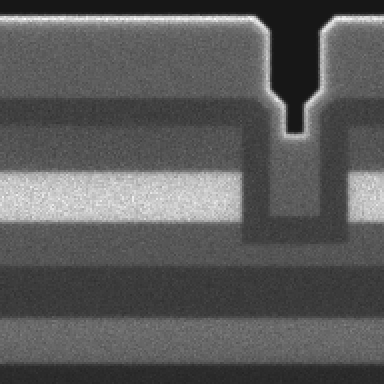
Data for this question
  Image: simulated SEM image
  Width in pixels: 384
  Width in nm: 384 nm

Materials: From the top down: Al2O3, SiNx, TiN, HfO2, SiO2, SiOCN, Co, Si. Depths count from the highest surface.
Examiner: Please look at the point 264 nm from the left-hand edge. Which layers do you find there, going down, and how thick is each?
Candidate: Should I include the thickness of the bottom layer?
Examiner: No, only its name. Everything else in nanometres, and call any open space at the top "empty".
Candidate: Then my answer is empty 10, Al2O3 82, SiNx 136, SiO2 22, SiOCN 52, Co 46, Si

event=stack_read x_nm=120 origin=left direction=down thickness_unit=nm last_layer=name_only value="Al2O3 82, SiNx 28, TiN 46, HfO2 50, SiO2 44, SiOCN 52, Co 46, Si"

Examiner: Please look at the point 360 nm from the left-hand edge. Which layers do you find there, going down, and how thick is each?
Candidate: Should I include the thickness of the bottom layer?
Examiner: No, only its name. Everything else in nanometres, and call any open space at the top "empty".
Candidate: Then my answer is Al2O3 82, SiNx 28, TiN 46, HfO2 50, SiO2 44, SiOCN 52, Co 46, Si